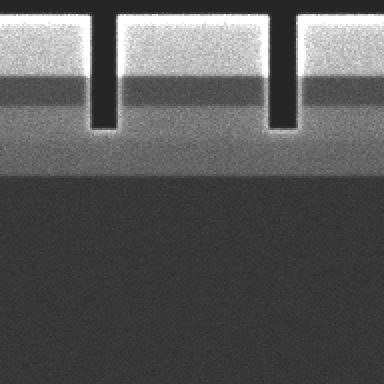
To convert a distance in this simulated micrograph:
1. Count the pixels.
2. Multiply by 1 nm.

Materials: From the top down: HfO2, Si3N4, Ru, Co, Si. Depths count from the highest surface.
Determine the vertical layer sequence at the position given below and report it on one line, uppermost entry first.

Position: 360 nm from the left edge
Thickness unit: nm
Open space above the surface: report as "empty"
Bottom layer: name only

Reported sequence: HfO2 60, Si3N4 30, Ru 34, Co 36, Si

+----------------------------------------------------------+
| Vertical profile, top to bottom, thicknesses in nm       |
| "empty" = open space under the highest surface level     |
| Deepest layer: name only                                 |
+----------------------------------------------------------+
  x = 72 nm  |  HfO2 60, Si3N4 30, Ru 34, Co 36, Si